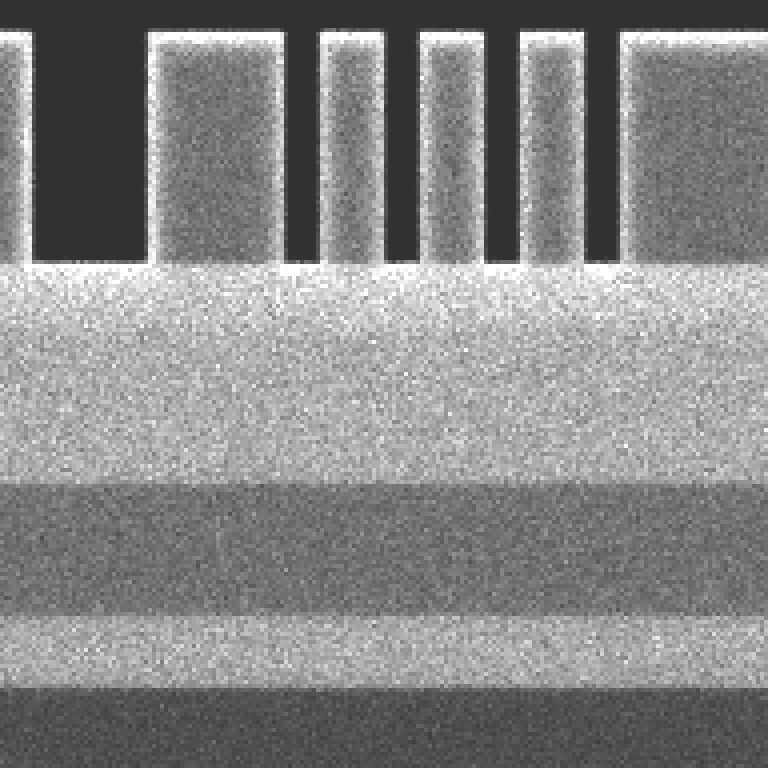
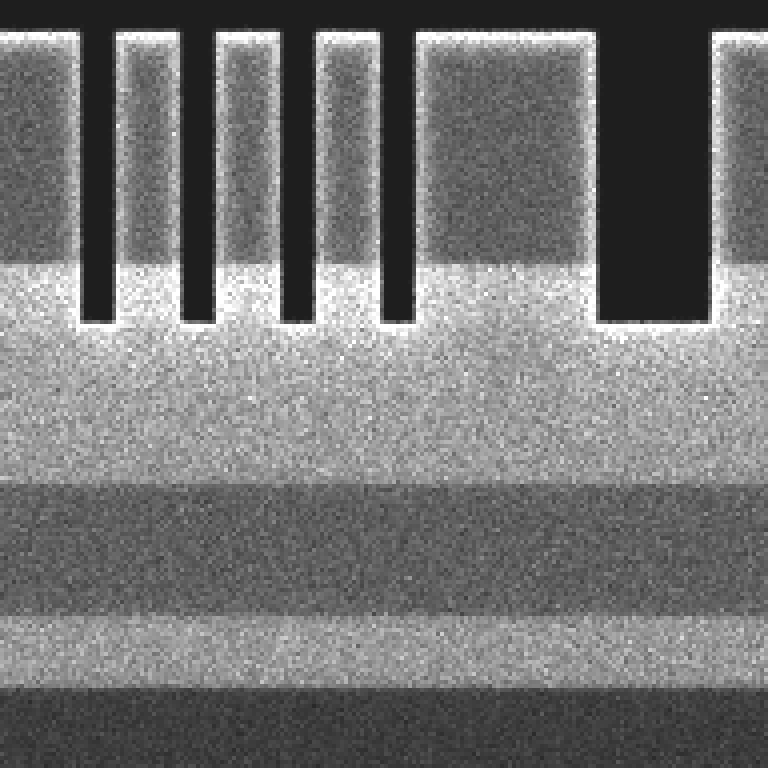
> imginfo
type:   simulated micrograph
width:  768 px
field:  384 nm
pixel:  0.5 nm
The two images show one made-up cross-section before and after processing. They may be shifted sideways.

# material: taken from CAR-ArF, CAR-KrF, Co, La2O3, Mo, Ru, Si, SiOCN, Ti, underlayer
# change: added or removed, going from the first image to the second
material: Ru
change: removed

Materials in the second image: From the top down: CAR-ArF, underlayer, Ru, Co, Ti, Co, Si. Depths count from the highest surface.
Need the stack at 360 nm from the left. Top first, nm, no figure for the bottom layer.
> CAR-ArF 74, underlayer 42, Ru 30, Co 80, Ti 66, Co 36, Si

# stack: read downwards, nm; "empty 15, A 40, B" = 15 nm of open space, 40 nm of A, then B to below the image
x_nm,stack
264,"CAR-ArF 74, underlayer 42, Ru 30, Co 80, Ti 66, Co 36, Si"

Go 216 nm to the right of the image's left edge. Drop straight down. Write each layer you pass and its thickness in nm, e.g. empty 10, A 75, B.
CAR-ArF 74, underlayer 42, Ru 30, Co 80, Ti 66, Co 36, Si